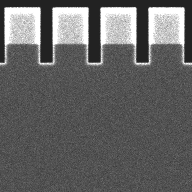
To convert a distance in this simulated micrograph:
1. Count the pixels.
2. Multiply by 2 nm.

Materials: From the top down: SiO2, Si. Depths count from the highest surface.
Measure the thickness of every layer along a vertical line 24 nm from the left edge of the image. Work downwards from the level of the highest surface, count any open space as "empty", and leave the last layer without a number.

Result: SiO2 72, Si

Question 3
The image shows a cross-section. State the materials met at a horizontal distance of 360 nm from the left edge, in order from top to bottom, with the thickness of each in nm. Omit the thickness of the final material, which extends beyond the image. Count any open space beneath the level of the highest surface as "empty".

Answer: SiO2 72, Si